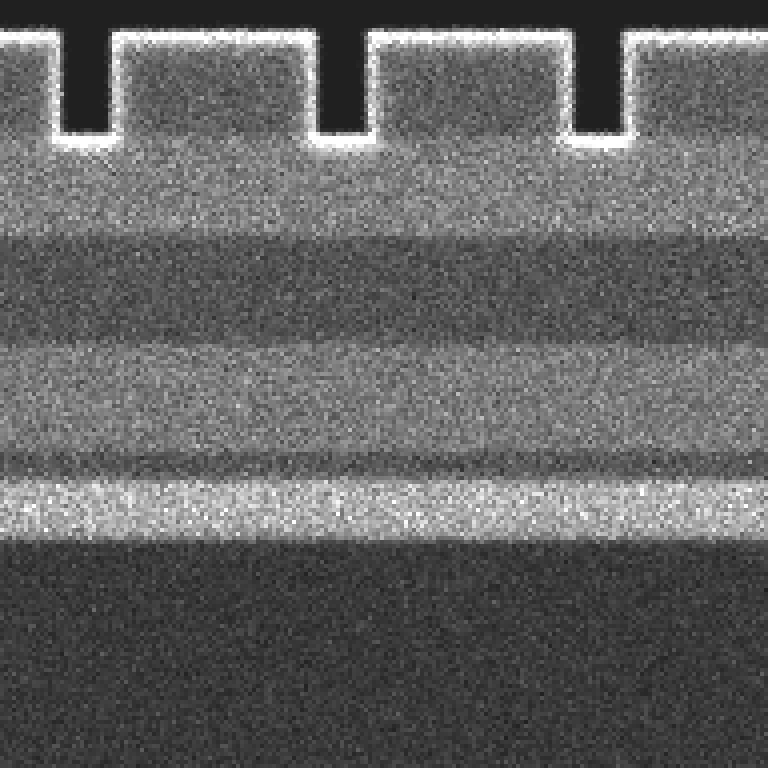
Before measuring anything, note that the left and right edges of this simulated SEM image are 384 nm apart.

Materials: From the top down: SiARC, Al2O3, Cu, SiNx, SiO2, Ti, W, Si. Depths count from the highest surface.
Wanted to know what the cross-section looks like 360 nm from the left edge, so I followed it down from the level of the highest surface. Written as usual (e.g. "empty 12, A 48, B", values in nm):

SiARC 52, Al2O3 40, Cu 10, SiNx 54, SiO2 54, Ti 14, W 30, Si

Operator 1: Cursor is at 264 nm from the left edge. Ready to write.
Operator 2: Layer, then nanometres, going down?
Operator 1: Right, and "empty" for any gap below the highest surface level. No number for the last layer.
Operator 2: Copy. SiARC 52, Al2O3 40, Cu 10, SiNx 54, SiO2 54, Ti 14, W 30, Si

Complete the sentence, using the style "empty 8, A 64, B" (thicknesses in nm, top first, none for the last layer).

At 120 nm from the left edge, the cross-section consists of SiARC 52, Al2O3 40, Cu 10, SiNx 54, SiO2 54, Ti 14, W 30, Si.